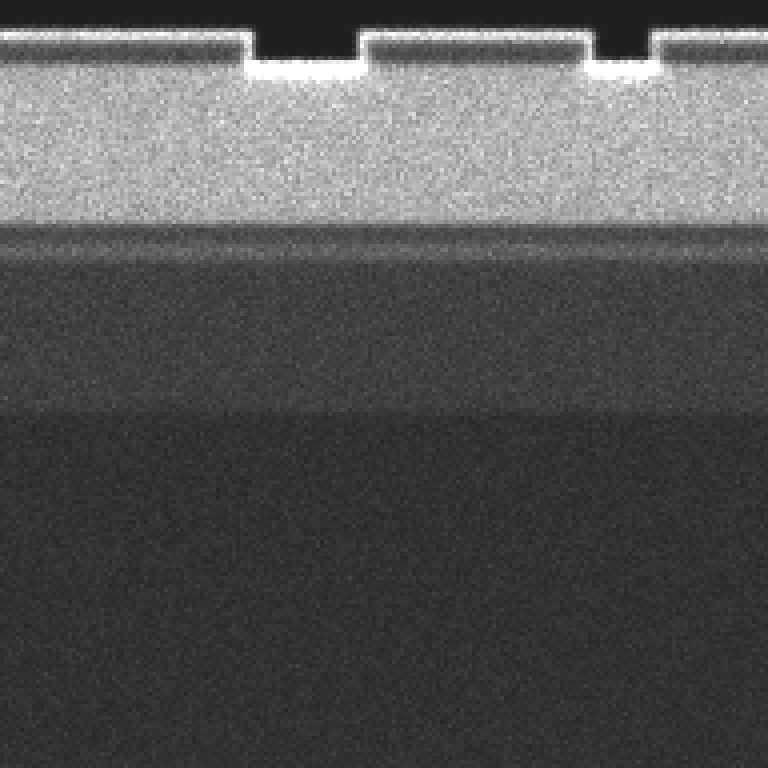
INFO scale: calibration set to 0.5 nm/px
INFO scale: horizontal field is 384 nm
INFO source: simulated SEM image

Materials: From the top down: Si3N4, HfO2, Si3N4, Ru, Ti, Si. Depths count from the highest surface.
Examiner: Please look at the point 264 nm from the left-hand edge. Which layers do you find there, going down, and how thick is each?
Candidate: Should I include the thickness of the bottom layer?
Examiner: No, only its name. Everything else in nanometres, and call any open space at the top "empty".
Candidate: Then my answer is Si3N4 16, HfO2 80, Si3N4 10, Ru 8, Ti 76, Si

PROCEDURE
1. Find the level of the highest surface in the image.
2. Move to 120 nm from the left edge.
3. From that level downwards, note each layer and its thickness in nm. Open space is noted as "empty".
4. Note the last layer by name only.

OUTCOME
Si3N4 16, HfO2 80, Si3N4 10, Ru 8, Ti 76, Si